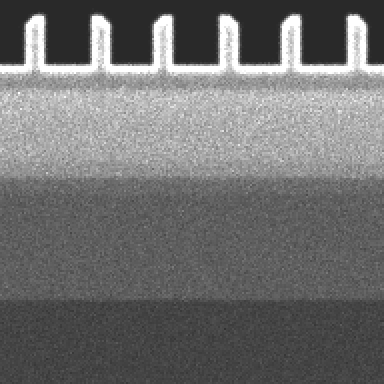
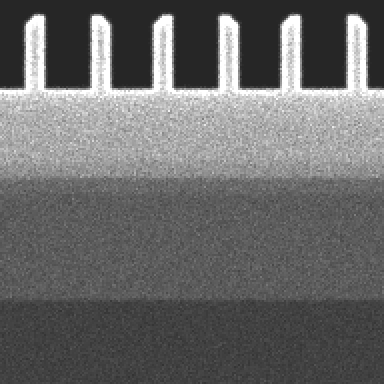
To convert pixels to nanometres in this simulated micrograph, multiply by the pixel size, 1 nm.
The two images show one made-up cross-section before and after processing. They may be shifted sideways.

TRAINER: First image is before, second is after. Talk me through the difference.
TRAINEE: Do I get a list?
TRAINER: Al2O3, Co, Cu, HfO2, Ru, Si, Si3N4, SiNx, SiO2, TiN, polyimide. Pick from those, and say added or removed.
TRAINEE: removed: Al2O3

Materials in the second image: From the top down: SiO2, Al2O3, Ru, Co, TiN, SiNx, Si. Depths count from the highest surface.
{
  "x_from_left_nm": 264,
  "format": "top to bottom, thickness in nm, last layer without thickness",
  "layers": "empty 74, Ru 72, Co 16, TiN 16, SiNx 106, Si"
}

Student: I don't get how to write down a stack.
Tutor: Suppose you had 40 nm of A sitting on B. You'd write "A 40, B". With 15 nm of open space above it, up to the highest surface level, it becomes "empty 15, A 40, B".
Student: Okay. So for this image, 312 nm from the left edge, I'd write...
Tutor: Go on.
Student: empty 74, Ru 72, Co 16, TiN 16, SiNx 106, Si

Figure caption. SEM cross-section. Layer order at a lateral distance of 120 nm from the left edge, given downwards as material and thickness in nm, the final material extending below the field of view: empty 74, Ru 72, Co 16, TiN 16, SiNx 106, Si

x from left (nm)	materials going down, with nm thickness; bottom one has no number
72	empty 74, Ru 72, Co 16, TiN 16, SiNx 106, Si